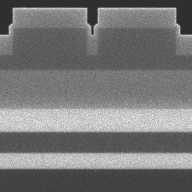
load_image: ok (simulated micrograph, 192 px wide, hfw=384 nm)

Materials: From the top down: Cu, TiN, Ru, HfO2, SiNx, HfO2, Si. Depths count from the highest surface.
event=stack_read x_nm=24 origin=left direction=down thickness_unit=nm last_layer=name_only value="empty 32, Cu 62, TiN 30, Ru 78, HfO2 46, SiNx 42, HfO2 32, Si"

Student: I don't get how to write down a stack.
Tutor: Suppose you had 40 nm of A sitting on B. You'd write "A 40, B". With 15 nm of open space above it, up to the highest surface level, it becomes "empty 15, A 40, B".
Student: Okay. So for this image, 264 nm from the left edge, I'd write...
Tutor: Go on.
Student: Cu 40, TiN 84, Ru 78, HfO2 46, SiNx 42, HfO2 32, Si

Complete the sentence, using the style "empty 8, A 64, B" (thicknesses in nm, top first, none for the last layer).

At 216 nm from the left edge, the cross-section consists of Cu 40, TiN 84, Ru 78, HfO2 46, SiNx 42, HfO2 32, Si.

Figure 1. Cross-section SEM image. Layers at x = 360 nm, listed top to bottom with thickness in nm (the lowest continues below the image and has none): empty 54, Cu 40, TiN 30, Ru 78, HfO2 46, SiNx 42, HfO2 32, Si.